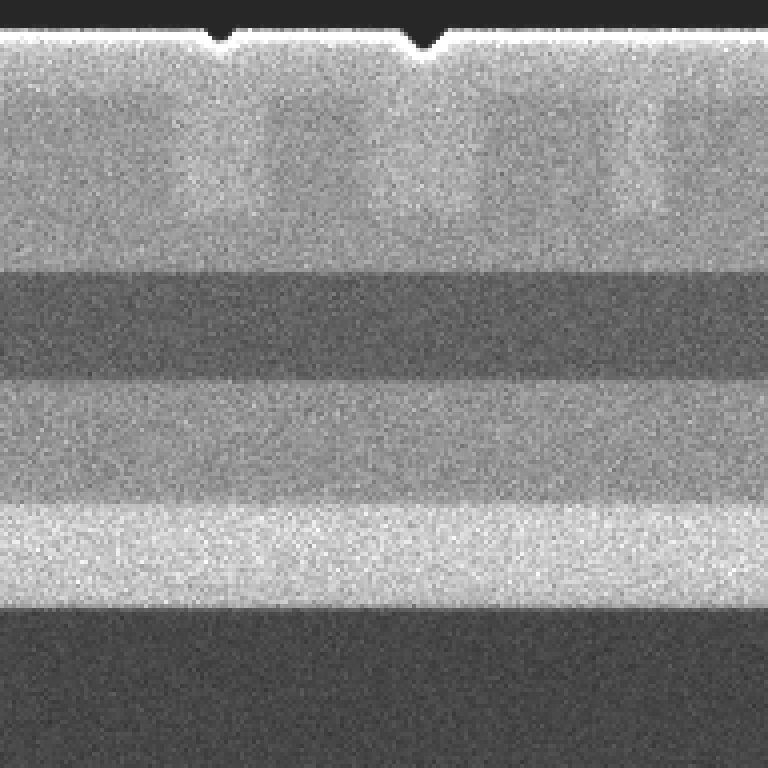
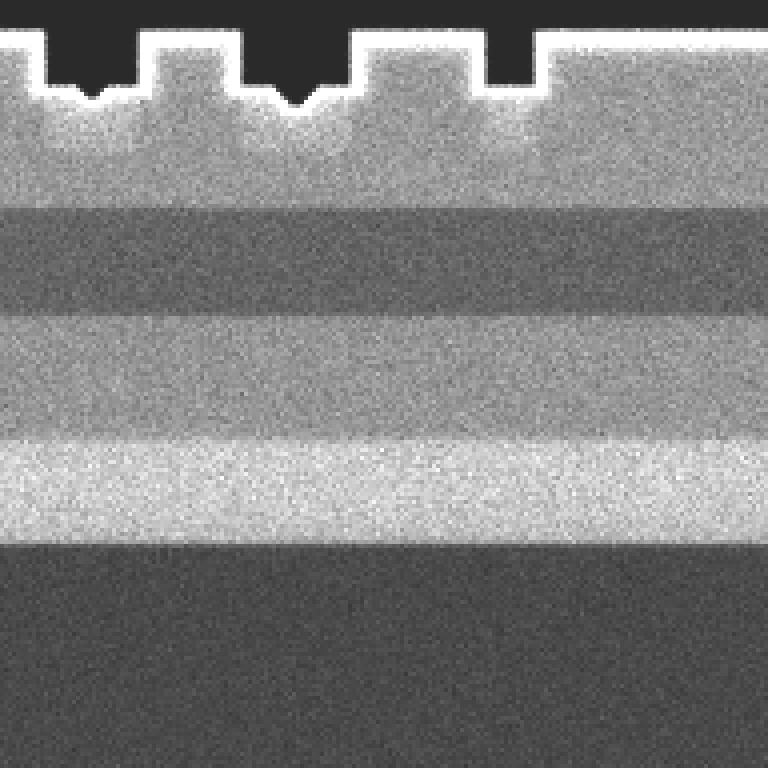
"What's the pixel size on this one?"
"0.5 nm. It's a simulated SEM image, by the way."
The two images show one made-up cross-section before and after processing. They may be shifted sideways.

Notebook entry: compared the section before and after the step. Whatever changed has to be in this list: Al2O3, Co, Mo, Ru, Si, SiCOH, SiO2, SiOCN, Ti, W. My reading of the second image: Ru removed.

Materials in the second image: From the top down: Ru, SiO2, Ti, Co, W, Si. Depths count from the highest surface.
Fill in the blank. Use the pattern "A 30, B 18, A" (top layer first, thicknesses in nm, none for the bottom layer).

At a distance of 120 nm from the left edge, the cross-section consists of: empty 28, Ru 32, SiO2 28, Ti 54, Co 62, W 52, Si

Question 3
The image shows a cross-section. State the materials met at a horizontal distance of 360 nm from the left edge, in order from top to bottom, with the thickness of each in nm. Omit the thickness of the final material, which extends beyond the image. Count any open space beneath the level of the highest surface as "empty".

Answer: SiO2 88, Ti 54, Co 62, W 52, Si